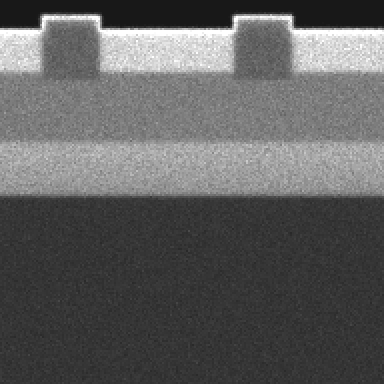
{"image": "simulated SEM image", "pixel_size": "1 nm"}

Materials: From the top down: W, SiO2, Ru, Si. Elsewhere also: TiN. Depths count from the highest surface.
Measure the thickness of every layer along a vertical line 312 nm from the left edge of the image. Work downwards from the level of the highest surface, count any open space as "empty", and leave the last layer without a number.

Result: empty 14, W 42, SiO2 70, Ru 54, Si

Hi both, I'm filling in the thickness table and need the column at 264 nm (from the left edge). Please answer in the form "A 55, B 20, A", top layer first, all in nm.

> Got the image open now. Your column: TiN 64, SiO2 62, Ru 54, Si